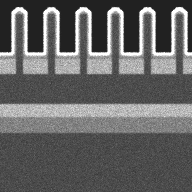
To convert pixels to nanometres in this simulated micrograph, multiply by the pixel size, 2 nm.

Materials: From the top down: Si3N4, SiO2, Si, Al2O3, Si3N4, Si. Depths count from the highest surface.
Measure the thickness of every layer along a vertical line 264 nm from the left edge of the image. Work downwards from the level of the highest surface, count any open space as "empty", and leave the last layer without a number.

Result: empty 90, Si3N4 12, SiO2 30, Si 60, Al2O3 26, Si3N4 32, Si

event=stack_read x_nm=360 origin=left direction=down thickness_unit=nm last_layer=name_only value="Si3N4 12, Si 180, Al2O3 26, Si3N4 32, Si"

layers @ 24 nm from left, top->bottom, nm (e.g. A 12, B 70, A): empty 8, Si3N4 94, SiO2 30, Si 60, Al2O3 26, Si3N4 32, Si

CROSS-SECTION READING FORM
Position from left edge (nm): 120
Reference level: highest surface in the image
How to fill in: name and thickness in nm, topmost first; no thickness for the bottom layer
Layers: empty 90, Si3N4 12, SiO2 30, Si 60, Al2O3 26, Si3N4 32, Si